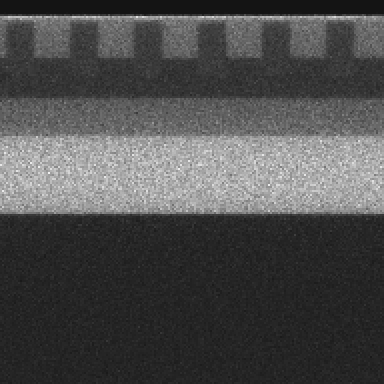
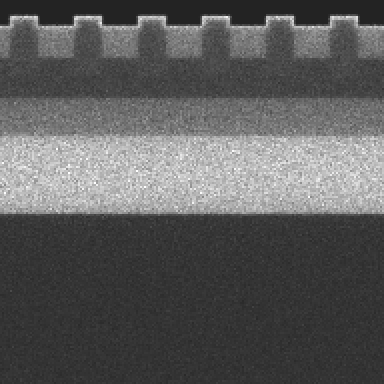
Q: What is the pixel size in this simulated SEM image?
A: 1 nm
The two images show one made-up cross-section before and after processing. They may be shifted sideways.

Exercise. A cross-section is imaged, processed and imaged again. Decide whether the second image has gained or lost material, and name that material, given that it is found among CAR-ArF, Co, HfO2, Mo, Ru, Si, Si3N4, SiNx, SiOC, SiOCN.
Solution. removed: Ru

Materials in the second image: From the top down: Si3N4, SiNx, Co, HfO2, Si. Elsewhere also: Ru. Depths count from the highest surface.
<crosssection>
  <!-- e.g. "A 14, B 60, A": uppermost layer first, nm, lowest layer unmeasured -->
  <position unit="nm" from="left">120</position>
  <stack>empty 10, Ru 32, SiNx 40, Co 38, HfO2 78, Si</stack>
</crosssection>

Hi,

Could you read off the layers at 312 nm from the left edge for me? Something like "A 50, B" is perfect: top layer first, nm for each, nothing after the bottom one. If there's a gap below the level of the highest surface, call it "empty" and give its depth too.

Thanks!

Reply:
empty 10, Ru 32, SiNx 40, Co 38, HfO2 78, Si